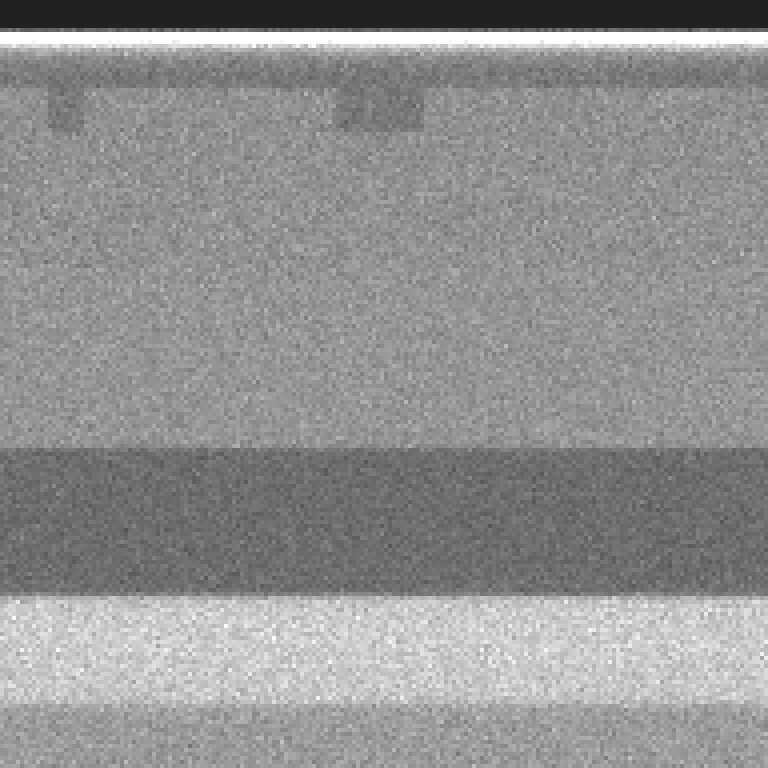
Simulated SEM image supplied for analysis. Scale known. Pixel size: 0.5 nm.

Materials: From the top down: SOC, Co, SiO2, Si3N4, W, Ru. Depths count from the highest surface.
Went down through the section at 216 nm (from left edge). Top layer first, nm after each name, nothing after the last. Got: SOC 28, Co 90, SiO2 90, Si3N4 74, W 54, Ru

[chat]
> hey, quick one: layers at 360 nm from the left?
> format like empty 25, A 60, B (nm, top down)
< SOC 28, Co 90, SiO2 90, Si3N4 74, W 54, Ru